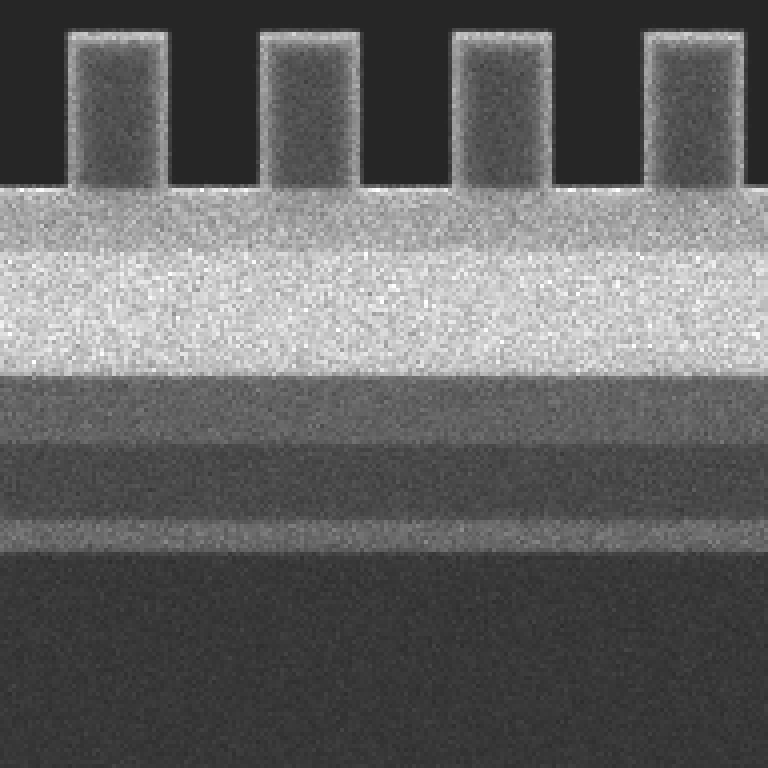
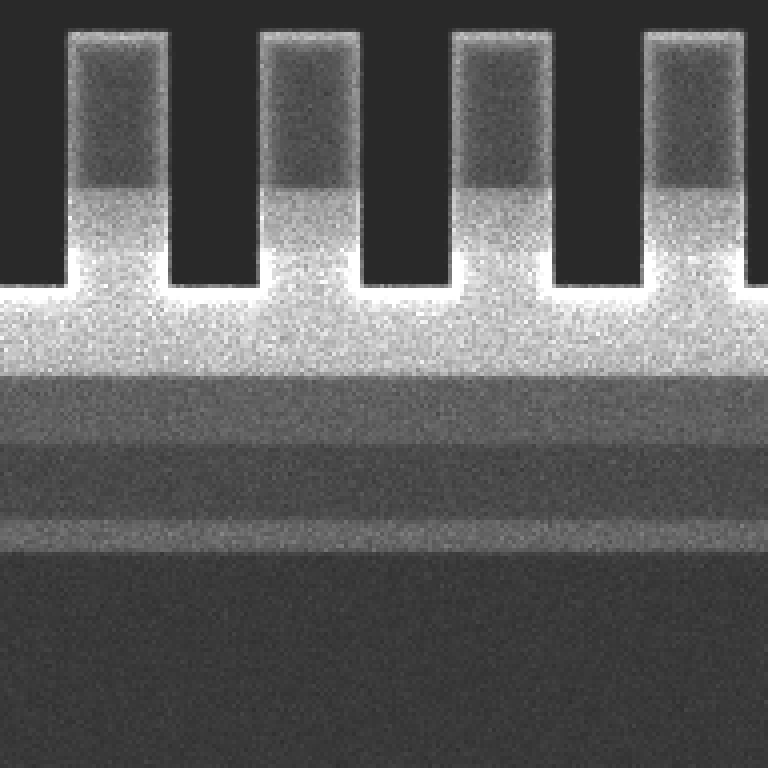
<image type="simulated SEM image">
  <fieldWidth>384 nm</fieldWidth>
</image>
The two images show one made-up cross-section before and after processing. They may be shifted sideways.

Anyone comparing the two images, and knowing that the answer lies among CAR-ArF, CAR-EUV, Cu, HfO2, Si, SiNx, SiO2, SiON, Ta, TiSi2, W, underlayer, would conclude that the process removed HfO2 and W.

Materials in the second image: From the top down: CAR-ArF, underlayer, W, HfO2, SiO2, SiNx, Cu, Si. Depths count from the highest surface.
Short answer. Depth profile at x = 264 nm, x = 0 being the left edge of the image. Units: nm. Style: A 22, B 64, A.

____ CAR-ArF 62, underlayer 16, W 32, HfO2 62, SiO2 34, SiNx 38, Cu 16, Si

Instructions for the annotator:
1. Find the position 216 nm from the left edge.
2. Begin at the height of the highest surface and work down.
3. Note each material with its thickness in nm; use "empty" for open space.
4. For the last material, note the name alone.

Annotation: empty 128, HfO2 44, SiO2 34, SiNx 38, Cu 16, Si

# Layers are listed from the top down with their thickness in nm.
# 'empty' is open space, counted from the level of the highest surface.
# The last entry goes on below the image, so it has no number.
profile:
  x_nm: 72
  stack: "CAR-ArF 62, underlayer 16, W 32, HfO2 62, SiO2 34, SiNx 38, Cu 16, Si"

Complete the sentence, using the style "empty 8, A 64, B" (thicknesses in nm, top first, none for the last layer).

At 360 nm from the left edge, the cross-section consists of CAR-ArF 62, underlayer 16, W 32, HfO2 62, SiO2 34, SiNx 38, Cu 16, Si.